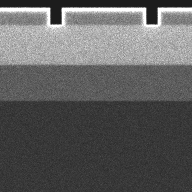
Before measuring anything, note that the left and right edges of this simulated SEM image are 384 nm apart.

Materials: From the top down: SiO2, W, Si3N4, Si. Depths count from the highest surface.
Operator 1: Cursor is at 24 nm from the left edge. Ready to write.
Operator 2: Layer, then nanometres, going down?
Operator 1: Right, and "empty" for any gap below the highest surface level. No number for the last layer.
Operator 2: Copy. SiO2 34, W 80, Si3N4 72, Si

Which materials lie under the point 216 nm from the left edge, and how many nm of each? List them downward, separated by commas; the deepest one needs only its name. SiO2 34, W 80, Si3N4 72, Si